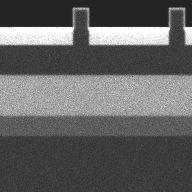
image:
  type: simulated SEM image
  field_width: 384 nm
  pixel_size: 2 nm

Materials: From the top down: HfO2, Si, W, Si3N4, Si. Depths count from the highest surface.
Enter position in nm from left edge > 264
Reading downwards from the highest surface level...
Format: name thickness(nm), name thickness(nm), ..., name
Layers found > empty 40, HfO2 34, Si 60, W 82, Si3N4 40, Si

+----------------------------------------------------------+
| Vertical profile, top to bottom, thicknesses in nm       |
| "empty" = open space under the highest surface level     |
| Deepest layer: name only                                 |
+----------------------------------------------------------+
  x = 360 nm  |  Si 134, W 82, Si3N4 40, Si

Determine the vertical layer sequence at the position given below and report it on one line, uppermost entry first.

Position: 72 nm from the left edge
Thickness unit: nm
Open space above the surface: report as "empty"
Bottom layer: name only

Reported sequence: empty 40, HfO2 34, Si 60, W 82, Si3N4 40, Si